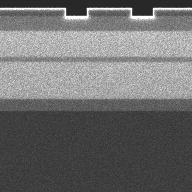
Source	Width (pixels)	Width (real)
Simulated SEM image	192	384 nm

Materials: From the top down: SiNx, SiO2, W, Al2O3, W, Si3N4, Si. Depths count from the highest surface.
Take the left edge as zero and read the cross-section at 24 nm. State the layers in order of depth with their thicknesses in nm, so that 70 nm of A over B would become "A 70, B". SiNx 16, SiO2 30, W 52, Al2O3 10, W 74, Si3N4 24, Si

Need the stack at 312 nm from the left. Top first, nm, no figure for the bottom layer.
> SiNx 16, SiO2 30, W 52, Al2O3 10, W 74, Si3N4 24, Si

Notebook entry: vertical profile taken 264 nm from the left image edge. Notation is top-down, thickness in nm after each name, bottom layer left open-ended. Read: empty 16, SiO2 30, W 52, Al2O3 10, W 74, Si3N4 24, Si